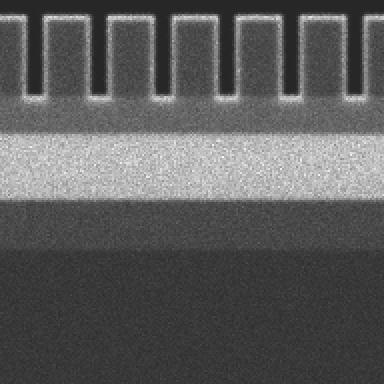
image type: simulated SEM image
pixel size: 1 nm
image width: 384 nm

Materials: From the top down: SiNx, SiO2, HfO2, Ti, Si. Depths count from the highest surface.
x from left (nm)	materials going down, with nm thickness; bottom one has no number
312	SiNx 80, SiO2 38, HfO2 66, Ti 50, Si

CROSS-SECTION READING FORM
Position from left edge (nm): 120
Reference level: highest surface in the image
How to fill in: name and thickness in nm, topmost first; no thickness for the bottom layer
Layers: SiNx 80, SiO2 38, HfO2 66, Ti 50, Si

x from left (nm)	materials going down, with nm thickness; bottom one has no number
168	empty 80, SiO2 38, HfO2 66, Ti 50, Si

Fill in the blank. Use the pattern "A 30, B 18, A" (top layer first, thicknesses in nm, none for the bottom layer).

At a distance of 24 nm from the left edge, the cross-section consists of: SiNx 80, SiO2 38, HfO2 66, Ti 50, Si